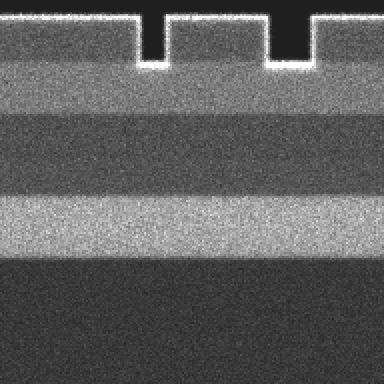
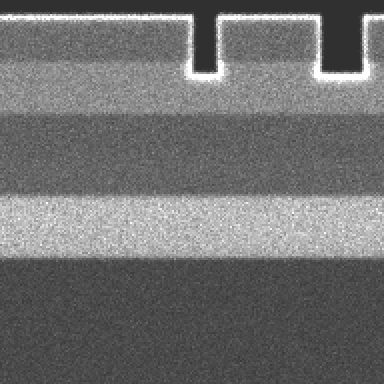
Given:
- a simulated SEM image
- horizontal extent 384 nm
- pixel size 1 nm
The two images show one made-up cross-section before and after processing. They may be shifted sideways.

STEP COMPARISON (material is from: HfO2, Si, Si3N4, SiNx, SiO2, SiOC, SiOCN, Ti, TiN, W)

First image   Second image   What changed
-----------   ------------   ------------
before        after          SiO2, removed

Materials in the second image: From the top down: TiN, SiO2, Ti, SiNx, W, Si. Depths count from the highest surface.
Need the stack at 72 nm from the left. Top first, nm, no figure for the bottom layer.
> TiN 46, SiO2 52, Ti 46, SiNx 36, W 62, Si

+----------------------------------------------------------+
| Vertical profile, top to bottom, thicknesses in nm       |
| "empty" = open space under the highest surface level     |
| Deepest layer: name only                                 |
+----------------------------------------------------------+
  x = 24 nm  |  TiN 46, SiO2 52, Ti 46, SiNx 36, W 62, Si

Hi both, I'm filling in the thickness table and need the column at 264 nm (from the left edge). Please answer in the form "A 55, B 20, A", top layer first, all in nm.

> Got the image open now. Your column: TiN 46, SiO2 52, Ti 46, SiNx 36, W 62, Si